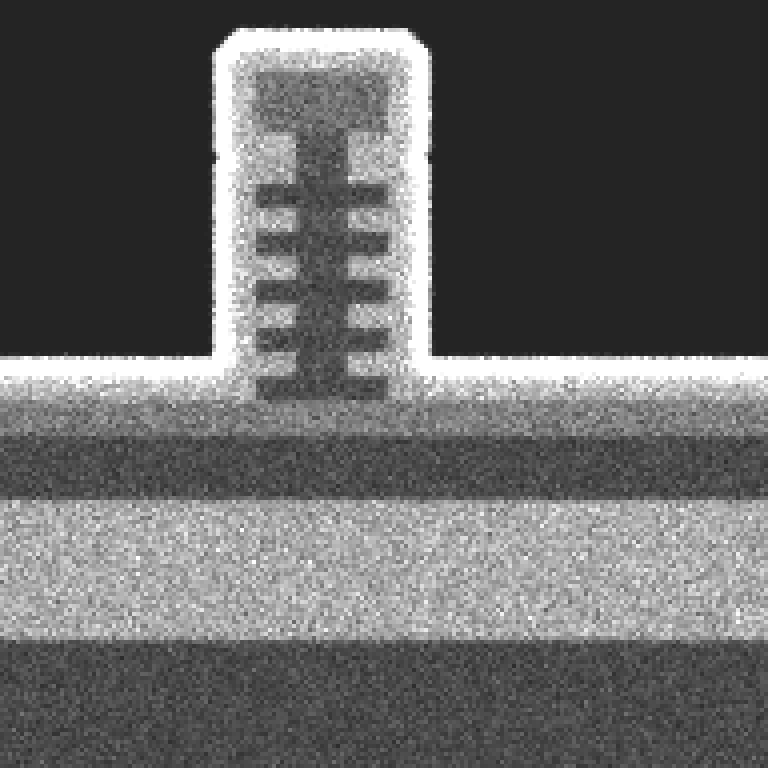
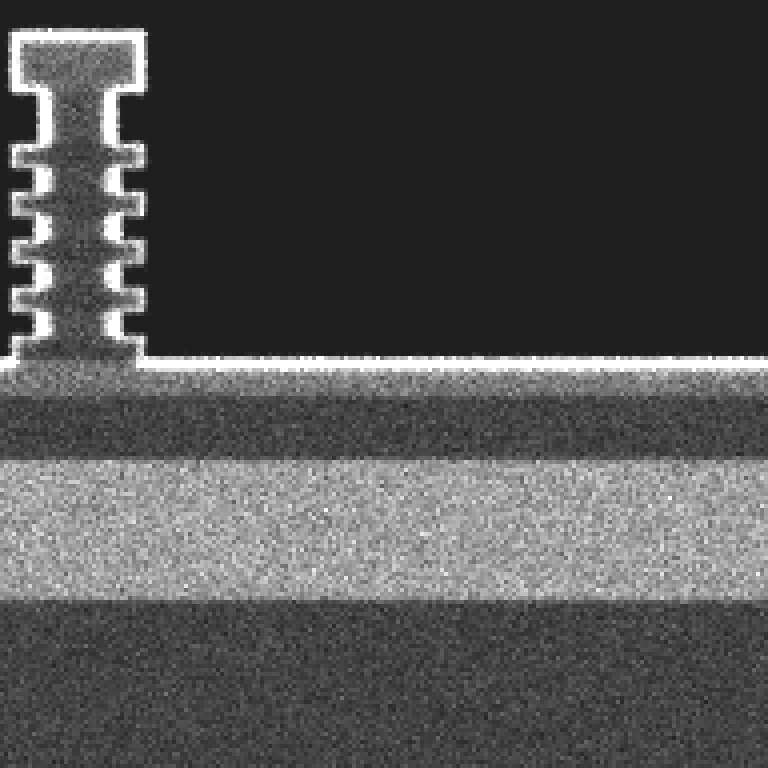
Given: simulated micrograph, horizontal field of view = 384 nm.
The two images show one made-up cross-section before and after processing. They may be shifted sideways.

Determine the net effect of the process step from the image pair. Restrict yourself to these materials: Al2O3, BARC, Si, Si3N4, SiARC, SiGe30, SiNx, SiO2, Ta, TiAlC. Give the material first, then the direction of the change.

Al2O3: removed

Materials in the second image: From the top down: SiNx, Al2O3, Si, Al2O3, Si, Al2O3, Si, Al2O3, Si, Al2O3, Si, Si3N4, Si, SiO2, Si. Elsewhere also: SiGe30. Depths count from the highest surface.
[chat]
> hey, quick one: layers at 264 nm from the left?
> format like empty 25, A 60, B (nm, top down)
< empty 164, Si3N4 18, Si 32, SiO2 70, Si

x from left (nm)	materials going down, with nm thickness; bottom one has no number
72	empty 164, Si3N4 18, Si 32, SiO2 70, Si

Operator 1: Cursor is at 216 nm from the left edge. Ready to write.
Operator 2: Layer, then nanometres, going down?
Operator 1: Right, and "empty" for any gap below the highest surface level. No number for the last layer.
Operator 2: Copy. empty 164, Si3N4 18, Si 32, SiO2 70, Si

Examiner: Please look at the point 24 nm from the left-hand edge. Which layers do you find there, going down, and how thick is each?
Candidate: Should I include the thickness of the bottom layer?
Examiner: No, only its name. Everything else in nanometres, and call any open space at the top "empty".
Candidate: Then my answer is SiNx 30, Al2O3 26, Si 12, Al2O3 12, Si 12, Al2O3 12, Si 12, Al2O3 12, Si 12, Al2O3 12, Si 12, Si3N4 18, Si 32, SiO2 70, Si